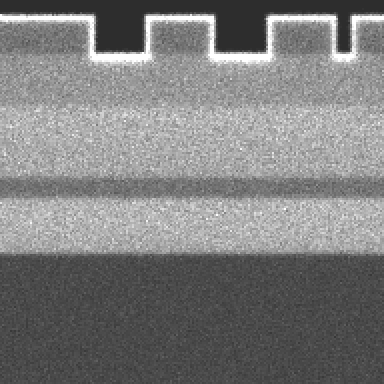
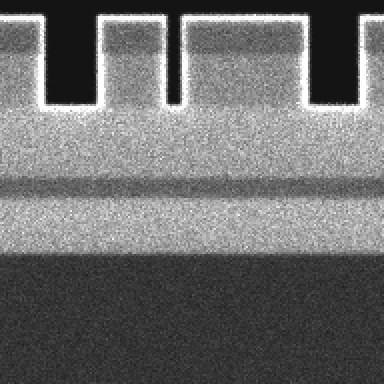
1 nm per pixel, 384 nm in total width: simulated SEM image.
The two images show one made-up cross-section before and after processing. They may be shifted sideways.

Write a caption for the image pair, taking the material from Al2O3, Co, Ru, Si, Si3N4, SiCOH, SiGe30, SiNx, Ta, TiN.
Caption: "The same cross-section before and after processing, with Al2O3 removed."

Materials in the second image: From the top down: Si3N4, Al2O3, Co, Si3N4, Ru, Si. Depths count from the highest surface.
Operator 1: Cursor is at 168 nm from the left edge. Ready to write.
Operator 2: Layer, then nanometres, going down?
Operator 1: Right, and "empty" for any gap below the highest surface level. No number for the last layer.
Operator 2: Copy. empty 90, Co 72, Si3N4 20, Ru 56, Si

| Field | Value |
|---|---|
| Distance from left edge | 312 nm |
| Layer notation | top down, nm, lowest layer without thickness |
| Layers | empty 90, Co 72, Si3N4 20, Ru 56, Si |